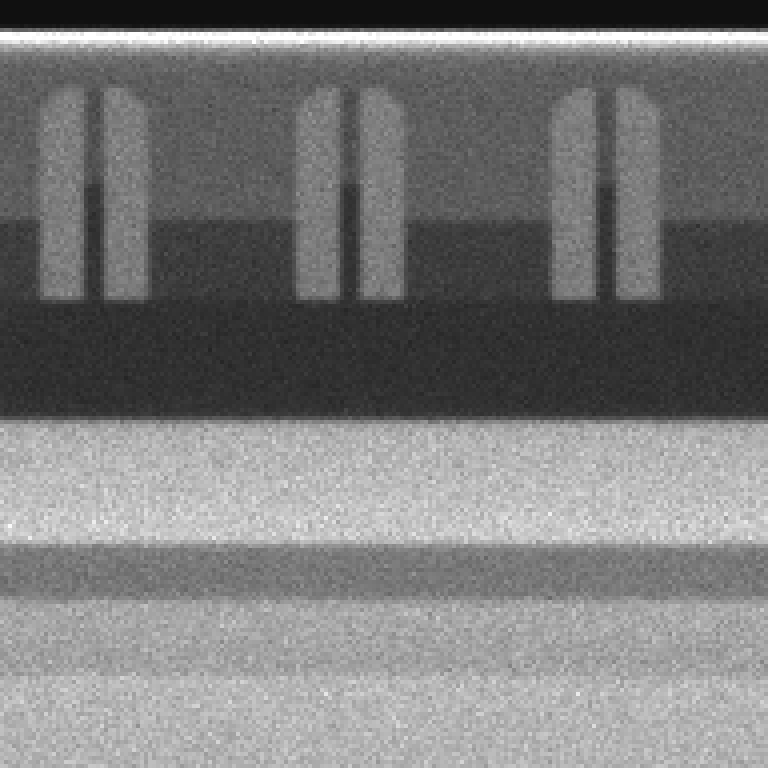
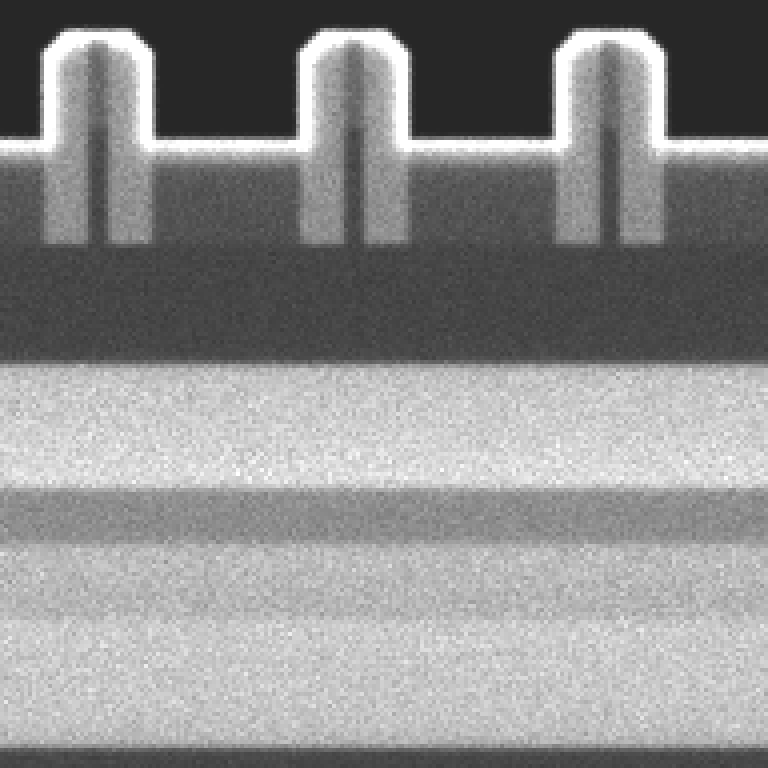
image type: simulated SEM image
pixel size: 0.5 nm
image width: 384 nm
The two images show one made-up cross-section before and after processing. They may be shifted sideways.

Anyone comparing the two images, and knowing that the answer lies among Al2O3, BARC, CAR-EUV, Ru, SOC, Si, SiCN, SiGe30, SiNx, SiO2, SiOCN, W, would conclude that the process removed SOC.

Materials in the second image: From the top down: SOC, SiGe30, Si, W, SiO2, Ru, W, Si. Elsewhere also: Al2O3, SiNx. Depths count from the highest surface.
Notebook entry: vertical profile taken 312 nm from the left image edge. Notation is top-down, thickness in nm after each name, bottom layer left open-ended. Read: Al2O3 106, Si 60, W 62, SiO2 28, Ru 38, W 64, Si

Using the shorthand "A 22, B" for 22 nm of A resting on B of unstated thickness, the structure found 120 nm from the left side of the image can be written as empty 54, SOC 12, SiGe30 40, Si 60, W 62, SiO2 28, Ru 38, W 64, Si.